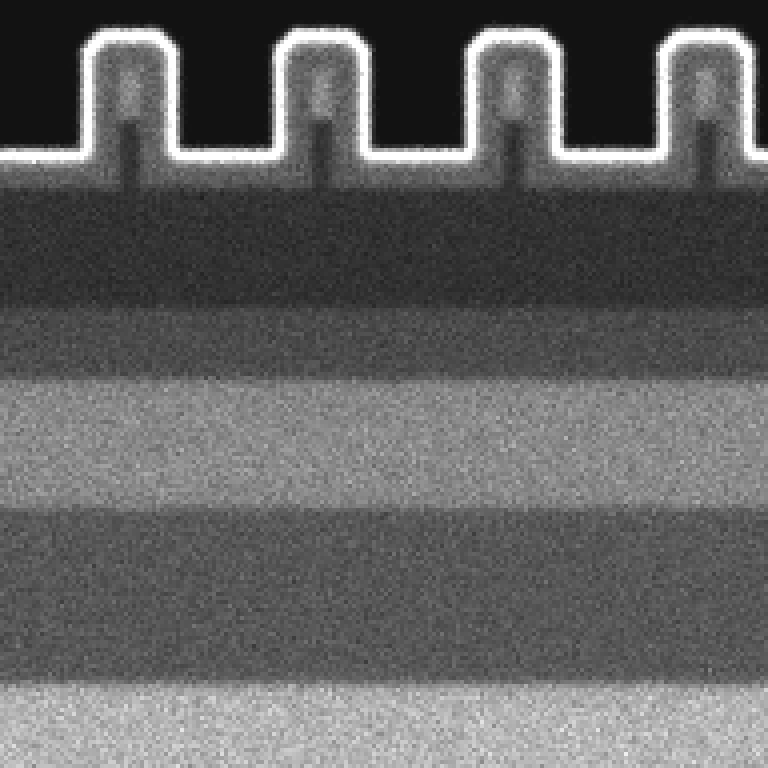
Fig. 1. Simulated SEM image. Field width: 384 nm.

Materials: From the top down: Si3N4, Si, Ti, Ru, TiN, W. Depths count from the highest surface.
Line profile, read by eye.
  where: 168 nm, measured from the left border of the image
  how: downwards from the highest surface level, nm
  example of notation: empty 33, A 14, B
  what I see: Si3N4 78, Si 60, Ti 36, Ru 64, TiN 88, W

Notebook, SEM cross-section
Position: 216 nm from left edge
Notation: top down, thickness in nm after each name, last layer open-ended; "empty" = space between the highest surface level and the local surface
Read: empty 60, Si3N4 18, Si 60, Ti 36, Ru 64, TiN 88, W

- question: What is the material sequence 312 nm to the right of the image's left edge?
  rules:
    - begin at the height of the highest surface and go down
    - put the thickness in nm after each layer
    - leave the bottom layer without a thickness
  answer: empty 60, Si3N4 18, Si 60, Ti 36, Ru 64, TiN 88, W